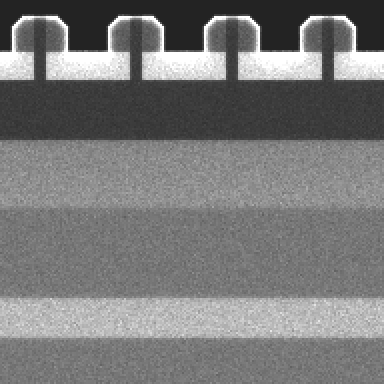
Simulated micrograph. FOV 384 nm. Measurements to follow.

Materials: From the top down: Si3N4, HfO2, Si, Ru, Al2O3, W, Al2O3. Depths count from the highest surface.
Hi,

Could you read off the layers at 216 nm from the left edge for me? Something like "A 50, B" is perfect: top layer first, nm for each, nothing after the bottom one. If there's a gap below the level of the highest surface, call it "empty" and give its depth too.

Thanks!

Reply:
Si3N4 36, HfO2 28, Si 60, Ru 68, Al2O3 90, W 40, Al2O3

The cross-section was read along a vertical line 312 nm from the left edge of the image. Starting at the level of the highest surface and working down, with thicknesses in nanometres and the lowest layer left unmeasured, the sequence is Si3N4 36, HfO2 28, Si 60, Ru 68, Al2O3 90, W 40, Al2O3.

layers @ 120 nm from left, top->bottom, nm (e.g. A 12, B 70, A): Si3N4 36, HfO2 28, Si 60, Ru 68, Al2O3 90, W 40, Al2O3